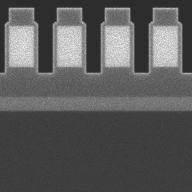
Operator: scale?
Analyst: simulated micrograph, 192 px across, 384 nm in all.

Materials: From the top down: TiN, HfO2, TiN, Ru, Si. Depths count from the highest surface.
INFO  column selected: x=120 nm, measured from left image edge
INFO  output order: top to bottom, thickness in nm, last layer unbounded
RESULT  TiN 36, HfO2 82, TiN 60, Ru 28, Si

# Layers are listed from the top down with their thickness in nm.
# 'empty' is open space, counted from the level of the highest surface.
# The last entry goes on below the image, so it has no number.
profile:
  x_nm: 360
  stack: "empty 30, TiN 148, Ru 28, Si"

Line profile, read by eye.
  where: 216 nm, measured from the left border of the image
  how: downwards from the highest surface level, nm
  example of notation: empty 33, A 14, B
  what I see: TiN 36, HfO2 82, TiN 60, Ru 28, Si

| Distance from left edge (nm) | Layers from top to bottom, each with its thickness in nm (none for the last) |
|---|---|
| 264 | empty 30, TiN 148, Ru 28, Si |